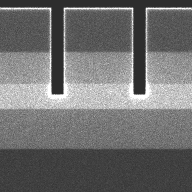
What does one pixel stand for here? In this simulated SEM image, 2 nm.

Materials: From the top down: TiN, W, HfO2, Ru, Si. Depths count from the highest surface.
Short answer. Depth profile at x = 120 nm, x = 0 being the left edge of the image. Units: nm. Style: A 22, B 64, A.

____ empty 174, HfO2 28, Ru 80, Si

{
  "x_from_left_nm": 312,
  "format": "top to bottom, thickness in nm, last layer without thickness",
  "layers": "TiN 88, W 64, HfO2 50, Ru 80, Si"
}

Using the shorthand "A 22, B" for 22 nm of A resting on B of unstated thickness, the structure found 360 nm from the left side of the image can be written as TiN 88, W 64, HfO2 50, Ru 80, Si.